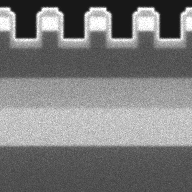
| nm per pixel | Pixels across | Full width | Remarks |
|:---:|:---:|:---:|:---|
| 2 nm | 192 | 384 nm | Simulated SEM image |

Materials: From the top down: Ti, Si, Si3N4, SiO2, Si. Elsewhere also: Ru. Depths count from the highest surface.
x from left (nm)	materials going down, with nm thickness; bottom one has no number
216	empty 8, Ti 72, Si 60, Si3N4 60, SiO2 76, Si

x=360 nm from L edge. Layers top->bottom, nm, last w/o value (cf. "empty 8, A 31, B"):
empty 62, Ti 18, Si 60, Si3N4 60, SiO2 76, Si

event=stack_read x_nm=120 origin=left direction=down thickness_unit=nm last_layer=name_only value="empty 8, Ti 72, Si 60, Si3N4 60, SiO2 76, Si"